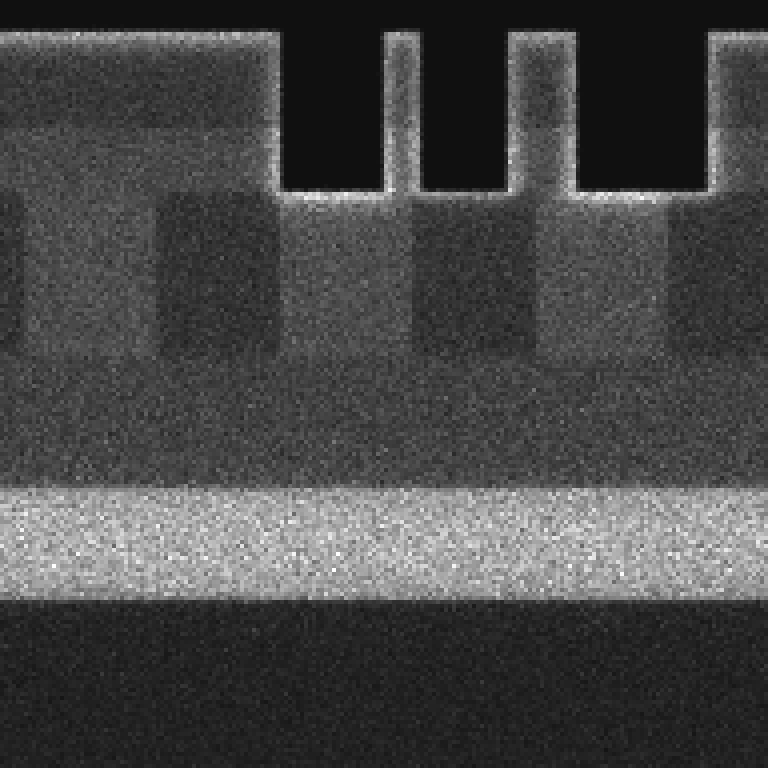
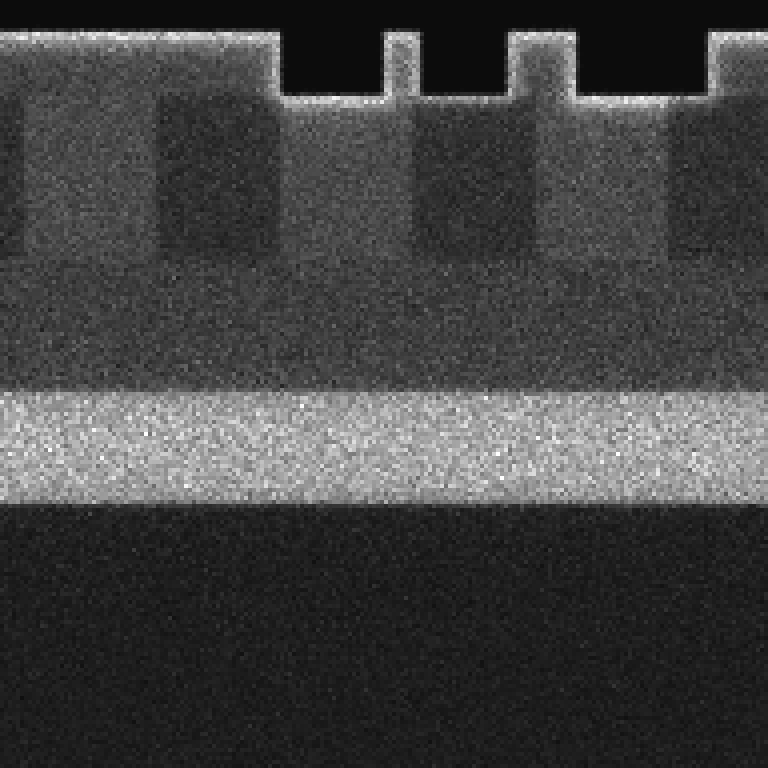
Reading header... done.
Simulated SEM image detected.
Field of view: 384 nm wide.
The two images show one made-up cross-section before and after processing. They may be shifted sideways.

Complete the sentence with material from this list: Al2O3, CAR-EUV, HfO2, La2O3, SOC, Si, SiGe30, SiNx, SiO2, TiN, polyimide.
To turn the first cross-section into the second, SOC must be removed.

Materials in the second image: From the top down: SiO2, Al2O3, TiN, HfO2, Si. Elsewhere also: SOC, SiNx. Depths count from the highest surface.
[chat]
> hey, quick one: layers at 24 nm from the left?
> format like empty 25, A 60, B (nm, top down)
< SiO2 32, Al2O3 82, TiN 66, HfO2 56, Si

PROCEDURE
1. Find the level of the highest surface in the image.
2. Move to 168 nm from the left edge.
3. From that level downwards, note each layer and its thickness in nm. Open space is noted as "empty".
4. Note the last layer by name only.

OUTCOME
empty 32, Al2O3 82, TiN 66, HfO2 56, Si